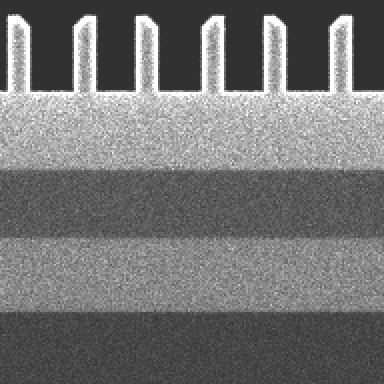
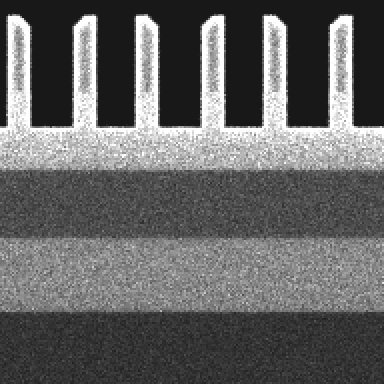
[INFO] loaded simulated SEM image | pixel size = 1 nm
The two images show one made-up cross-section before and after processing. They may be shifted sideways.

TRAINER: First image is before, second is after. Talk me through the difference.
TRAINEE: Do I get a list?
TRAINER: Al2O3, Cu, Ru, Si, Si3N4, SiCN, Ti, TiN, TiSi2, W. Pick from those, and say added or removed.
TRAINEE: removed: W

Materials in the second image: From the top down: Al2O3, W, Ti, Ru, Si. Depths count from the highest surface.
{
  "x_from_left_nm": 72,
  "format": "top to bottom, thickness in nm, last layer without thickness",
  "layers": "empty 112, W 42, Ti 68, Ru 74, Si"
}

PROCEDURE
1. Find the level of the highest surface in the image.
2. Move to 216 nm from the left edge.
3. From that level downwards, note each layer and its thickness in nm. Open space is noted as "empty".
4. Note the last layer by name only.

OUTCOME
Al2O3 76, W 78, Ti 68, Ru 74, Si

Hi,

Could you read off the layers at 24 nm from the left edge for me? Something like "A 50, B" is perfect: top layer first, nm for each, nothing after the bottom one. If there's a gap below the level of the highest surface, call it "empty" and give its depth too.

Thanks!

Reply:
empty 6, Al2O3 70, W 78, Ti 68, Ru 74, Si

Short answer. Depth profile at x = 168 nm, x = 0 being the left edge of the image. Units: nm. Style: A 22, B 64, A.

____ empty 112, W 42, Ti 68, Ru 74, Si